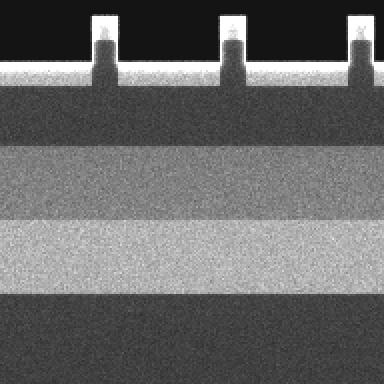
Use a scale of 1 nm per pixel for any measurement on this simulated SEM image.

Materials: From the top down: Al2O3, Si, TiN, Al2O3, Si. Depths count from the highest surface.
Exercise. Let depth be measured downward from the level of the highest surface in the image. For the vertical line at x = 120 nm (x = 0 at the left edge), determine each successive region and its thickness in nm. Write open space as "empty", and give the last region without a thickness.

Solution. empty 46, Al2O3 24, Si 60, TiN 74, Al2O3 74, Si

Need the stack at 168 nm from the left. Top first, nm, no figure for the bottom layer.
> empty 46, Al2O3 24, Si 60, TiN 74, Al2O3 74, Si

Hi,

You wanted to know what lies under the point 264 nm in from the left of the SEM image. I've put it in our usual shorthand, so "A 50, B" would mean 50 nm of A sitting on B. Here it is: empty 46, Al2O3 24, Si 60, TiN 74, Al2O3 74, Si